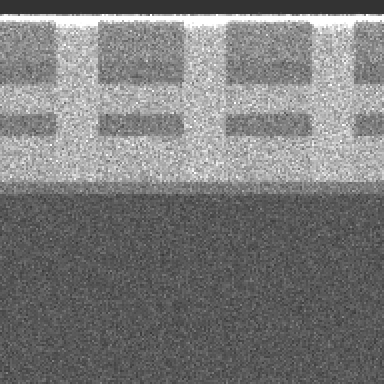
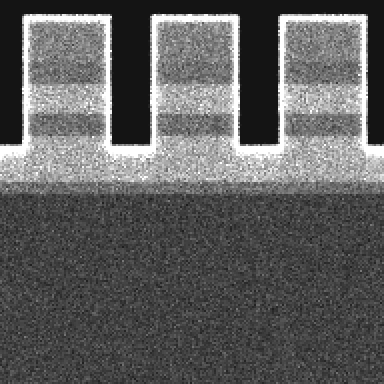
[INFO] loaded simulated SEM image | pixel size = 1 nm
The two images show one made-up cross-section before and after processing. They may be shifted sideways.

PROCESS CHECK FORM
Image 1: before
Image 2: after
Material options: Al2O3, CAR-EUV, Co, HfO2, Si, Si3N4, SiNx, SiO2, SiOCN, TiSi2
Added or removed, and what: removed, SiO2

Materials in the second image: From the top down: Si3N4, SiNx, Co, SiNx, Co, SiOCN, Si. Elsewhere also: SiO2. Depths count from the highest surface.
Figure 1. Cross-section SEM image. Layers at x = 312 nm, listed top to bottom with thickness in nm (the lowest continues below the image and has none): Si3N4 46, SiNx 22, Co 30, SiNx 22, Co 46, SiOCN 12, Si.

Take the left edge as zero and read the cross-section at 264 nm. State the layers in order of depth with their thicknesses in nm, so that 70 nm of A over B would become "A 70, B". empty 130, SiO2 36, SiOCN 12, Si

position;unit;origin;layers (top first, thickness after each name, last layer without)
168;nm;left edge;Si3N4 46, SiNx 22, Co 30, SiNx 22, Co 46, SiOCN 12, Si